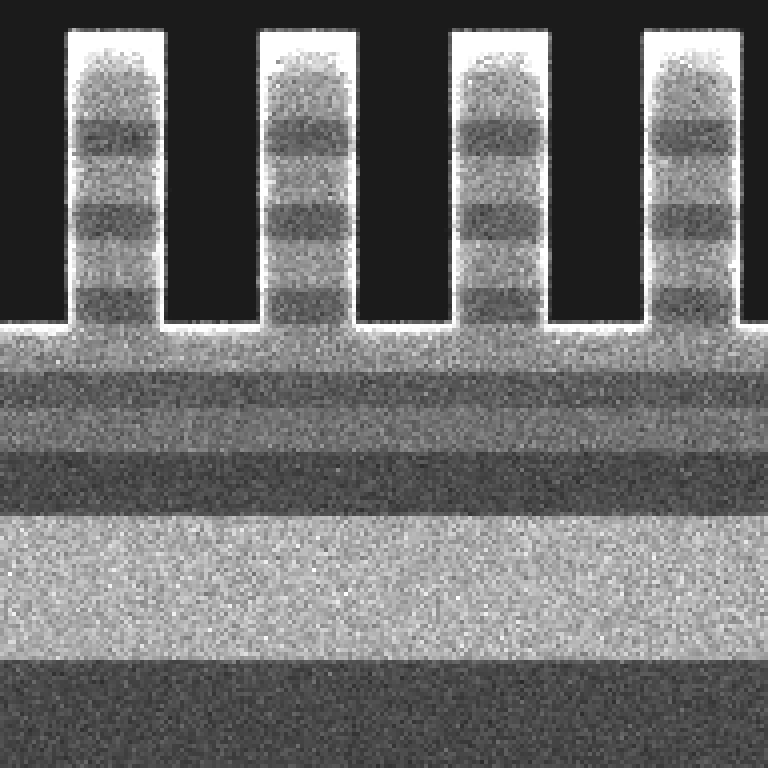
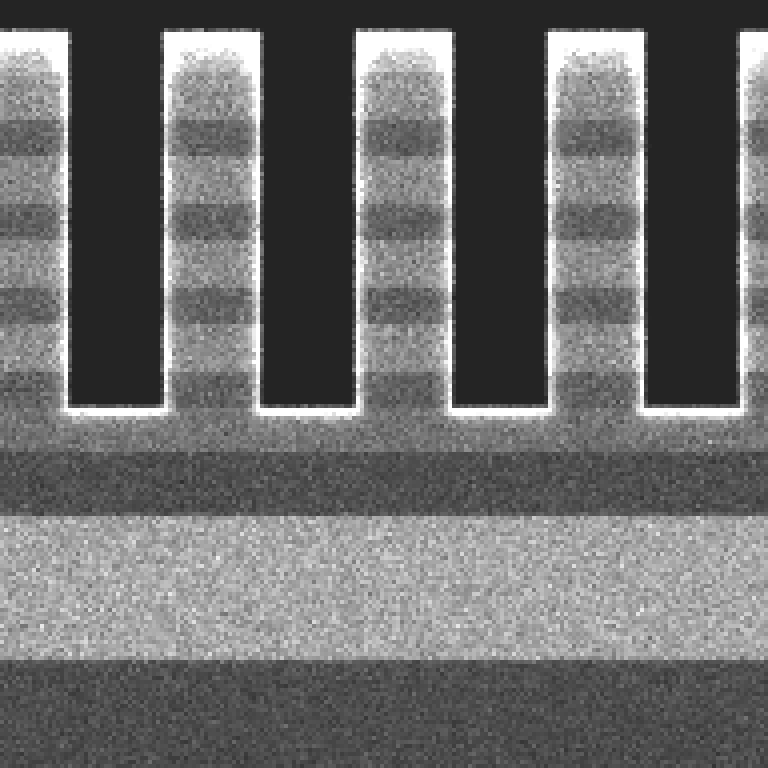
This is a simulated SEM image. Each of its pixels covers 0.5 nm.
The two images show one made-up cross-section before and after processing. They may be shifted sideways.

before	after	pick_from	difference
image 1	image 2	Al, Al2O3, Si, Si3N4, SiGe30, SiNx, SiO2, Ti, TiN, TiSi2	SiGe30 and TiN removed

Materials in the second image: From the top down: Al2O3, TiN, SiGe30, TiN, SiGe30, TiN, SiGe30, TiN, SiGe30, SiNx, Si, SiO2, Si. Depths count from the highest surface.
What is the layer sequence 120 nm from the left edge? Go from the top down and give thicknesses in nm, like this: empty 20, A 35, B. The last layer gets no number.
Al2O3 20, TiN 24, SiGe30 18, TiN 24, SiGe30 18, TiN 24, SiGe30 18, TiN 24, SiGe30 18, SiNx 22, Si 32, SiO2 72, Si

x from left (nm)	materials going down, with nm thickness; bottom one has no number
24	Al2O3 20, TiN 24, SiGe30 18, TiN 24, SiGe30 18, TiN 24, SiGe30 18, TiN 24, SiGe30 18, SiNx 22, Si 32, SiO2 72, Si